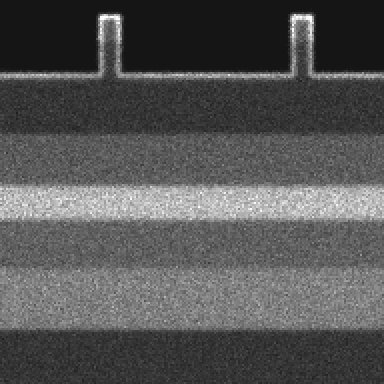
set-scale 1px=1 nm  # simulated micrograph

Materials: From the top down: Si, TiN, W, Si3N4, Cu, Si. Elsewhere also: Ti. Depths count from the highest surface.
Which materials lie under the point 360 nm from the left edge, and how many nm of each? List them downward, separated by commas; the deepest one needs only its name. empty 58, Si 60, TiN 52, W 34, Si3N4 48, Cu 62, Si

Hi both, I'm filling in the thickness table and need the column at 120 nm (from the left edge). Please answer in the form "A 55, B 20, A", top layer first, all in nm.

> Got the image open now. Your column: empty 58, Si 60, TiN 52, W 34, Si3N4 48, Cu 62, Si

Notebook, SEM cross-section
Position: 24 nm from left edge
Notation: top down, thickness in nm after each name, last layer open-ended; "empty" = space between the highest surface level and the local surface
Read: empty 58, Si 60, TiN 52, W 34, Si3N4 48, Cu 62, Si